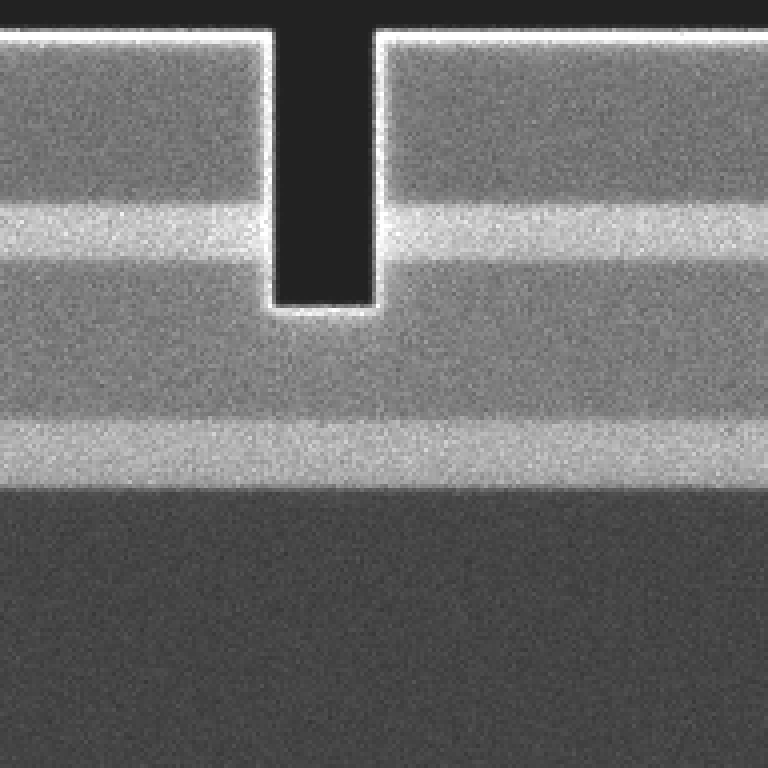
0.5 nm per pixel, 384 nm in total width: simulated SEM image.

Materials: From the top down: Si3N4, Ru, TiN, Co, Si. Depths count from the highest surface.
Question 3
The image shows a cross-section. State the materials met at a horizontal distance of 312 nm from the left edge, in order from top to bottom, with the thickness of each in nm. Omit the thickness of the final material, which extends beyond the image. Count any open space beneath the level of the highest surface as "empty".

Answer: Si3N4 86, Ru 28, TiN 80, Co 34, Si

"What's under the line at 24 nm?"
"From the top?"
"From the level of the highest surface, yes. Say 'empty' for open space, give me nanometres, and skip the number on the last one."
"Si3N4 86, Ru 28, TiN 80, Co 34, Si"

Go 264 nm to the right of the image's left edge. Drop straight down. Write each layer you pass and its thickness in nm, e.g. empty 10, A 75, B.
Si3N4 86, Ru 28, TiN 80, Co 34, Si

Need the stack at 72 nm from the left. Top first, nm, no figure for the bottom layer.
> Si3N4 86, Ru 28, TiN 80, Co 34, Si